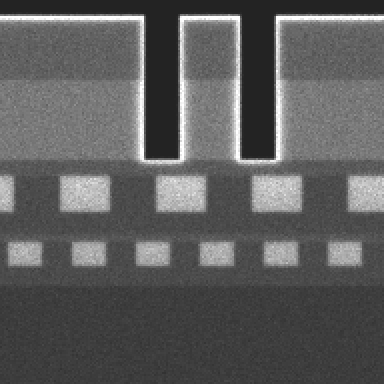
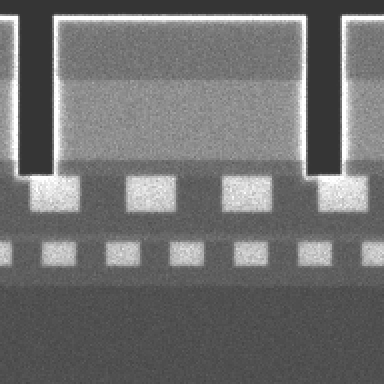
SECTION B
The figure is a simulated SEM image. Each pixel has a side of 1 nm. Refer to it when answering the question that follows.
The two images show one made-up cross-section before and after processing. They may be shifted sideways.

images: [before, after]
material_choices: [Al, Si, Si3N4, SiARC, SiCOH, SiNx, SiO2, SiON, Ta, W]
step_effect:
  removed: SiNx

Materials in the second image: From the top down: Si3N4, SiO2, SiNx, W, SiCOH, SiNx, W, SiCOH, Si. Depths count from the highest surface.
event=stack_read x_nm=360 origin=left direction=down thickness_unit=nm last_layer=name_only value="Si3N4 64, SiO2 80, SiNx 16, W 36, SiCOH 22, SiNx 8, SiCOH 44, Si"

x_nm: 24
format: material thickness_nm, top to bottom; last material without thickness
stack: empty 160, SiCOH 58, SiNx 8, SiCOH 44, Si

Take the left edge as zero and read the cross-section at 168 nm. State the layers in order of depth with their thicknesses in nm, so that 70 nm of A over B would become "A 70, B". Si3N4 64, SiO2 80, SiNx 16, W 36, SiCOH 22, SiNx 8, SiCOH 44, Si